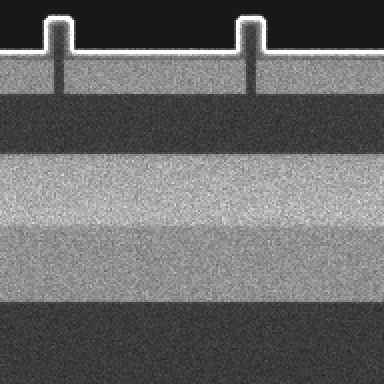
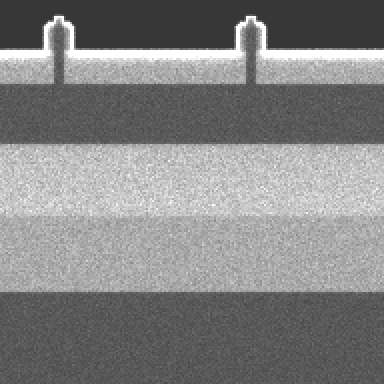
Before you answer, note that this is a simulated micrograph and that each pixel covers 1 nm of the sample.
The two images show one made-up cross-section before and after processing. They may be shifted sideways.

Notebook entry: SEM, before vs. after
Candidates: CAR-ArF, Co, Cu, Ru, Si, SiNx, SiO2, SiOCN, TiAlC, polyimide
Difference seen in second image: SiOCN removed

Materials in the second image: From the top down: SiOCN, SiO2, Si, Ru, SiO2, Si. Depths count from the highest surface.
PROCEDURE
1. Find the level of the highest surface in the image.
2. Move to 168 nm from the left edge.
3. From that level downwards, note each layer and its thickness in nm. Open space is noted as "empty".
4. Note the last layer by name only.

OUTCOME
empty 34, SiO2 34, Si 60, Ru 72, SiO2 76, Si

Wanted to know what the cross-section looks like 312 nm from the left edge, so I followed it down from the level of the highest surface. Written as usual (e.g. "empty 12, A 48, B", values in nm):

empty 34, SiO2 34, Si 60, Ru 72, SiO2 76, Si